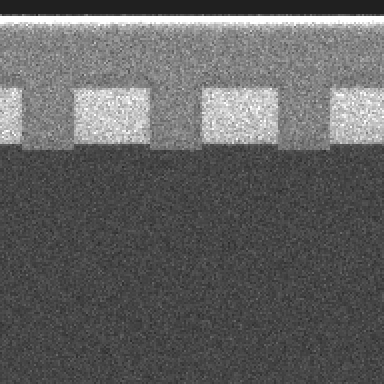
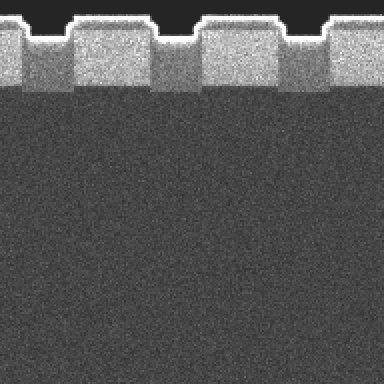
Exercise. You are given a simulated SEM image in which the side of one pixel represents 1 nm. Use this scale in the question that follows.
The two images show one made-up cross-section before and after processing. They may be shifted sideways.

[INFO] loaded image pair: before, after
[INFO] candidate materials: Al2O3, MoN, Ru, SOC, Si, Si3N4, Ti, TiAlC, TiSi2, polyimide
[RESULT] removed SOC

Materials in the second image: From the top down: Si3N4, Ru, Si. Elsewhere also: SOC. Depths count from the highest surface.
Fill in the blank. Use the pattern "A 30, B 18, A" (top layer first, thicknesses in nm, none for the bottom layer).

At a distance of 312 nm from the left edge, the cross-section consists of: empty 20, SOC 42, Si3N4 14, Si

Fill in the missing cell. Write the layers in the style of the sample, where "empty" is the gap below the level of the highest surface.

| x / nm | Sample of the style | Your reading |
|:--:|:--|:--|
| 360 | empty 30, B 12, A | Si3N4 14, Ru 56, Si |